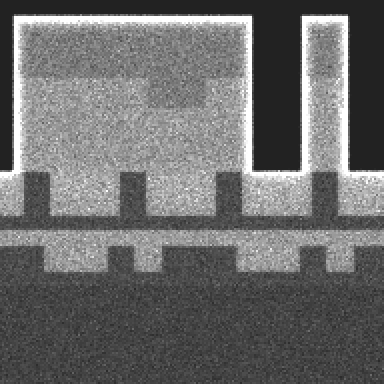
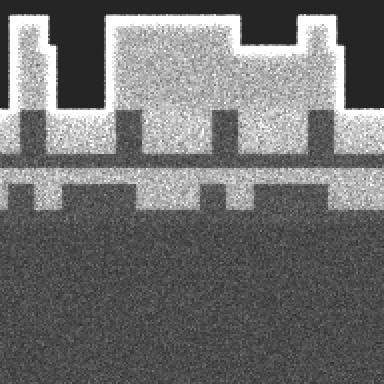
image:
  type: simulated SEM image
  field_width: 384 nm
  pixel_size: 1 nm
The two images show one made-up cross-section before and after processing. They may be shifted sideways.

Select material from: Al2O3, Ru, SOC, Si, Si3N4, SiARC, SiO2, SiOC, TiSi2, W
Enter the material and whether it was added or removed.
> SOC / removed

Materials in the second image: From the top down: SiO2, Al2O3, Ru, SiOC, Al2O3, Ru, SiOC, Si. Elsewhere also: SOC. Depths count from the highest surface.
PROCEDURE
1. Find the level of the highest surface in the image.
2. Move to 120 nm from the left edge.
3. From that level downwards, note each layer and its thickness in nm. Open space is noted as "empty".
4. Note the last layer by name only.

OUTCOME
SiO2 84, Al2O3 10, SiOC 58, Al2O3 16, SiOC 40, Si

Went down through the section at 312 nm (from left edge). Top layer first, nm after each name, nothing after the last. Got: SiO2 84, Al2O3 10, SiOC 58, Al2O3 16, SiOC 40, Si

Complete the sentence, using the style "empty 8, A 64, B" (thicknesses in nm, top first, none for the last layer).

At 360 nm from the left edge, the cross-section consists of empty 94, Ru 44, SiOC 14, Al2O3 16, Ru 26, SiOC 14, Si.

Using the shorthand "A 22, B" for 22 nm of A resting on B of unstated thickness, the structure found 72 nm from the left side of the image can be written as empty 94, Ru 44, SiOC 14, Al2O3 16, SiOC 40, Si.